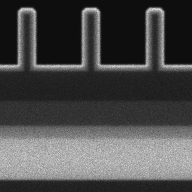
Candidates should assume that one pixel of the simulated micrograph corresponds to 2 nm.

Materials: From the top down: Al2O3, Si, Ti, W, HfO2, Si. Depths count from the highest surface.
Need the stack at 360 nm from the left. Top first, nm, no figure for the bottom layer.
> empty 114, Al2O3 12, Si 60, Ti 50, W 26, HfO2 82, Si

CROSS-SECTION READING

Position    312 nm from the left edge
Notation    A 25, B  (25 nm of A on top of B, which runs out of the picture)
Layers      Al2O3 12, Si 174, Ti 50, W 26, HfO2 82, Si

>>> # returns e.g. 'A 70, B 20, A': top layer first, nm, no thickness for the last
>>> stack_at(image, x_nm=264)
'empty 114, Al2O3 12, Si 60, Ti 50, W 26, HfO2 82, Si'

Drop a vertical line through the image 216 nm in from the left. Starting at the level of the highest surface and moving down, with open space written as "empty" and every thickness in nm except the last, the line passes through empty 114, Al2O3 12, Si 60, Ti 50, W 26, HfO2 82, Si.